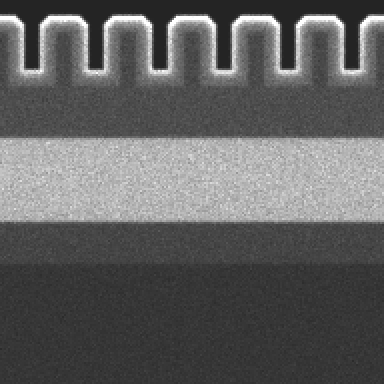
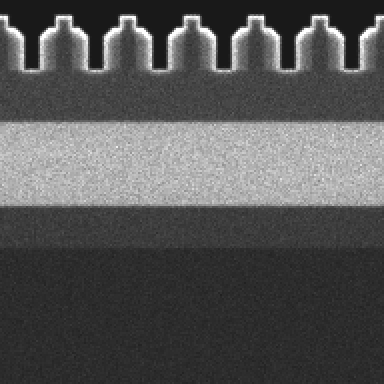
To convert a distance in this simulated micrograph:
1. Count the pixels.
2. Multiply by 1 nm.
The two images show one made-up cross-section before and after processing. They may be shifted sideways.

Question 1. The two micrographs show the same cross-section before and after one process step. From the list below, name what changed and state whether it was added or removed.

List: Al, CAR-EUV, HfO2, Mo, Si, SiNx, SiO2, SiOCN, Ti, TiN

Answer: SiO2, removed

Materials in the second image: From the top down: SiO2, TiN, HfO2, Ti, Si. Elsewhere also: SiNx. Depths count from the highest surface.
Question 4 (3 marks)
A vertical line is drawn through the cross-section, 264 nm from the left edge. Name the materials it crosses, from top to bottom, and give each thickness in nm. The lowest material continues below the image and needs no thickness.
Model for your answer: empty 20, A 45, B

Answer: empty 12, SiO2 42, TiN 52, HfO2 84, Ti 42, Si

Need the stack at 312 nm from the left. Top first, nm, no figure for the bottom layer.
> SiNx 54, TiN 52, HfO2 84, Ti 42, Si